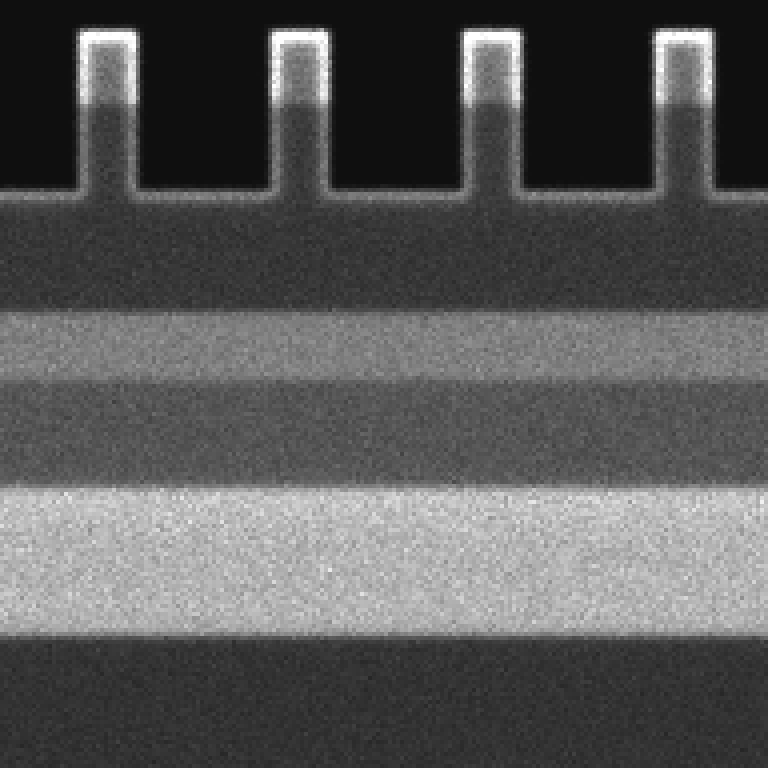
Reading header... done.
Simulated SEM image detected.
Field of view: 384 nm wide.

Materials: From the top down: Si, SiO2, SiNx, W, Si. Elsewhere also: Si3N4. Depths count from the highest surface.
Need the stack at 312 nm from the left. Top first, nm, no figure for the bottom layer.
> empty 80, Si 60, SiO2 34, SiNx 54, W 74, Si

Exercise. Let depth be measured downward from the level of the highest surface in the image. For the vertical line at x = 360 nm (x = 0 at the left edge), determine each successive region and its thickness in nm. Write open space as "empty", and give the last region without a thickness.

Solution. empty 80, Si 60, SiO2 34, SiNx 54, W 74, Si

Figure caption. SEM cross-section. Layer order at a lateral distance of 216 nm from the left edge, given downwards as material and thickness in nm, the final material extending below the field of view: empty 80, Si 60, SiO2 34, SiNx 54, W 74, Si